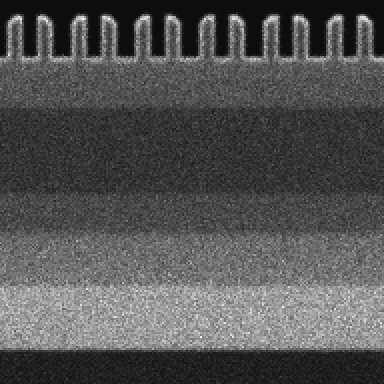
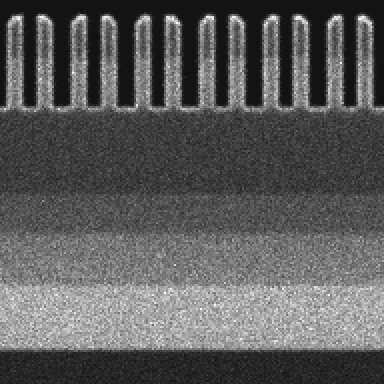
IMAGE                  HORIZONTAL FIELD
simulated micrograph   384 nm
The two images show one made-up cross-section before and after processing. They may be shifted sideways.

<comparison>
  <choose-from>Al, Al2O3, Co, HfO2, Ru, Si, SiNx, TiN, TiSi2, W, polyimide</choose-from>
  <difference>Ru removed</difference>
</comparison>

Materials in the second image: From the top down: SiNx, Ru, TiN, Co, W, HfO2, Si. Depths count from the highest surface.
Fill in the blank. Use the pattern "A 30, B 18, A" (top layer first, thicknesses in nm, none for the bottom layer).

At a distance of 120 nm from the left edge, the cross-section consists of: empty 92, TiN 86, Co 40, W 52, HfO2 64, Si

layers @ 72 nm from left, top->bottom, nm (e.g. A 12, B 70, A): empty 6, SiNx 36, Ru 50, TiN 86, Co 40, W 52, HfO2 64, Si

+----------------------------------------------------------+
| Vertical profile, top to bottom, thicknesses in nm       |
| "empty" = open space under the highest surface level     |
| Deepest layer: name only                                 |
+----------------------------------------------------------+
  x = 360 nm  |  SiNx 42, Ru 50, TiN 86, Co 40, W 52, HfO2 64, Si